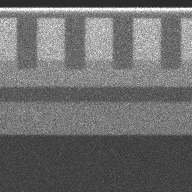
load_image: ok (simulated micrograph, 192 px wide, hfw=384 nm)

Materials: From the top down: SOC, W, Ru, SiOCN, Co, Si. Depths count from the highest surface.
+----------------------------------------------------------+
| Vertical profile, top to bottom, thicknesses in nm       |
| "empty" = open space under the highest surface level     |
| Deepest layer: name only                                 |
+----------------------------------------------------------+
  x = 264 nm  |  SOC 122, Ru 36, SiOCN 30, Co 66, Si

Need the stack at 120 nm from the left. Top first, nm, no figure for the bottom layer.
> SOC 20, W 84, Ru 54, SiOCN 30, Co 66, Si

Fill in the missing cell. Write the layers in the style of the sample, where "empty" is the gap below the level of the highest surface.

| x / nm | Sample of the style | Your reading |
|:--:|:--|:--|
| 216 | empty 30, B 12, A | SOC 20, W 84, Ru 54, SiOCN 30, Co 66, Si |